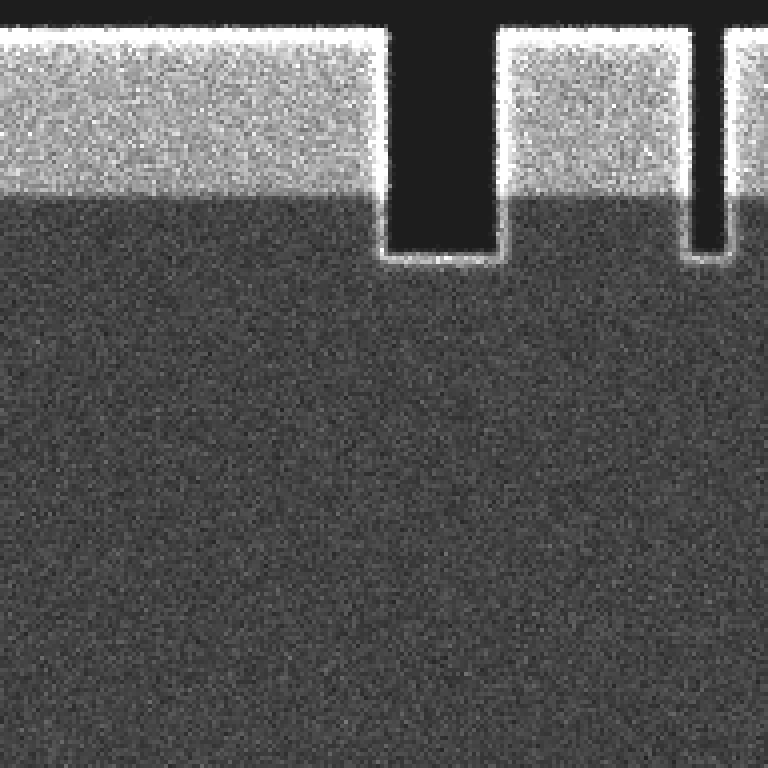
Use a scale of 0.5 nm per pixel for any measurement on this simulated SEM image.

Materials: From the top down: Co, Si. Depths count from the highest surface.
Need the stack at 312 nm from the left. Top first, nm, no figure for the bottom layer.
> Co 82, Si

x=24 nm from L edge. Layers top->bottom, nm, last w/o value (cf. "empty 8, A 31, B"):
Co 82, Si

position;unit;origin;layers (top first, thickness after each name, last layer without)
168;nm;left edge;Co 82, Si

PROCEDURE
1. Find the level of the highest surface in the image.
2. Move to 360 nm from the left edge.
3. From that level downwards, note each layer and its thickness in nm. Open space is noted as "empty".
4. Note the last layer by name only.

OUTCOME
empty 112, Si